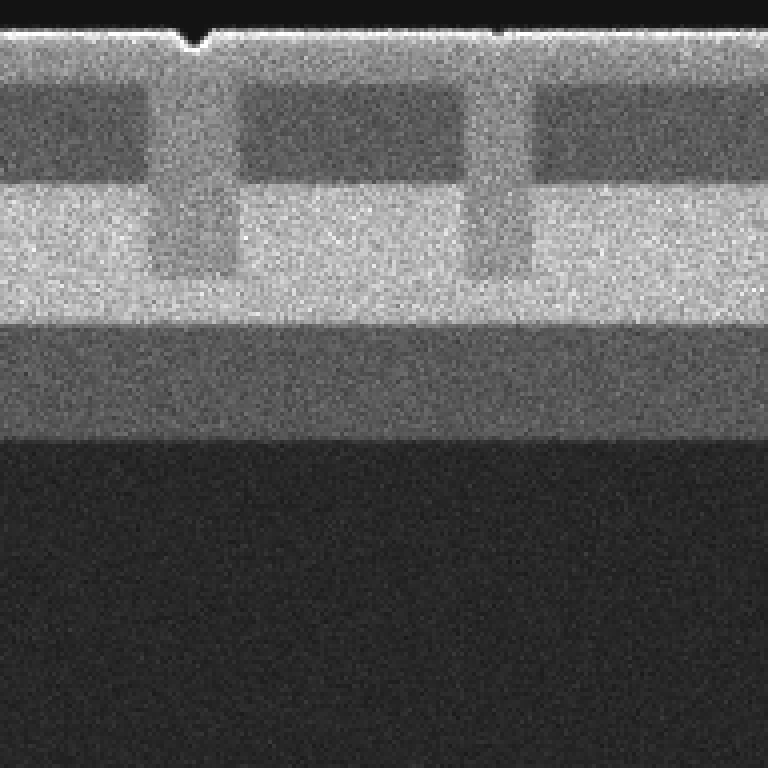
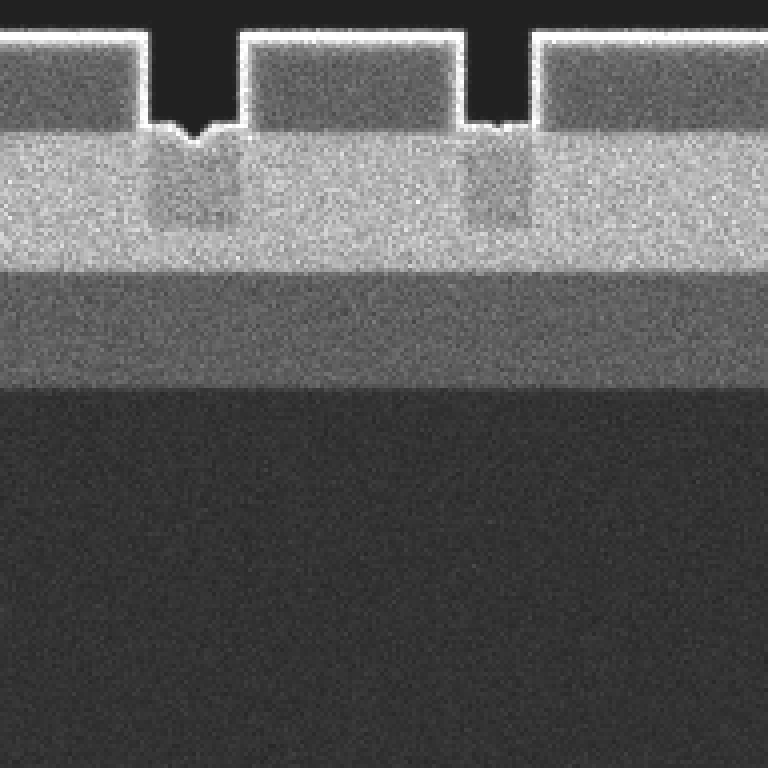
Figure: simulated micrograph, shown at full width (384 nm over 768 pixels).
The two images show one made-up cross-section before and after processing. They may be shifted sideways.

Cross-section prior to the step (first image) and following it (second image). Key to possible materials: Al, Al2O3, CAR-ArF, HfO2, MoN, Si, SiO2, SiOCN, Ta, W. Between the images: W was removed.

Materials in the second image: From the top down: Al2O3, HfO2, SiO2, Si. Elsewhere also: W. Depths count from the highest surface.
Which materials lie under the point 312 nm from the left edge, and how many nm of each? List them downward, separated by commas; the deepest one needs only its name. Al2O3 50, HfO2 70, SiO2 58, Si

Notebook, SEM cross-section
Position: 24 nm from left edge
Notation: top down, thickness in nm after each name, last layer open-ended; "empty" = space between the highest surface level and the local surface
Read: Al2O3 50, HfO2 70, SiO2 58, Si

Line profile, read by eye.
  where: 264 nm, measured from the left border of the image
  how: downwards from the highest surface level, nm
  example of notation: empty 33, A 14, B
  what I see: empty 46, W 52, HfO2 22, SiO2 58, Si